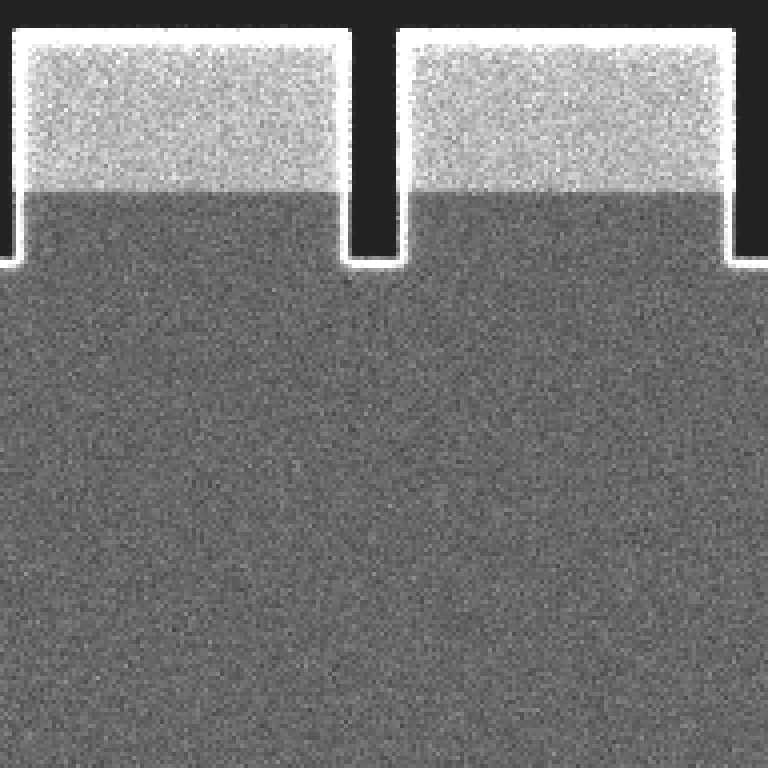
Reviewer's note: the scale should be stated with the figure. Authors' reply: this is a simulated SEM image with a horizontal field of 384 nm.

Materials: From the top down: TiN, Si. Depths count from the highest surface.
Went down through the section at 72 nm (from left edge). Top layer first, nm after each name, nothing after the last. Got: TiN 80, Si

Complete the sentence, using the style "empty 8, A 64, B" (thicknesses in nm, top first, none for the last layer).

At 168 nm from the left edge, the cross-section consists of TiN 80, Si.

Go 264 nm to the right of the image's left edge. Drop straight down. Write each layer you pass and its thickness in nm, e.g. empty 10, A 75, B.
TiN 80, Si